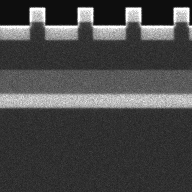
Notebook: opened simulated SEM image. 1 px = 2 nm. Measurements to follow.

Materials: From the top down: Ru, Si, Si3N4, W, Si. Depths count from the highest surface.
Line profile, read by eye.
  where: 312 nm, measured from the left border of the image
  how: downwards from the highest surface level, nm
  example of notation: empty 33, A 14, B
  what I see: empty 36, Ru 28, Si 60, Si3N4 48, W 28, Si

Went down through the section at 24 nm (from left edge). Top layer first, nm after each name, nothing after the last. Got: empty 36, Ru 28, Si 60, Si3N4 48, W 28, Si